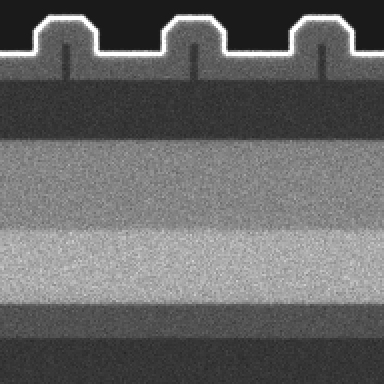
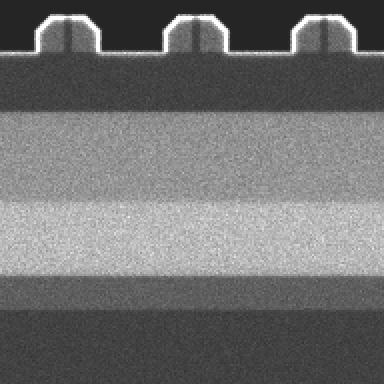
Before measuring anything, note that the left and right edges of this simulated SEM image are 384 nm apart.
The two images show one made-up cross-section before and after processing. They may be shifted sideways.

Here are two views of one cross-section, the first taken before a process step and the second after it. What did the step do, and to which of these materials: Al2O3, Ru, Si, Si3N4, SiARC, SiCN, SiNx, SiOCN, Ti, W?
It removed Si3N4.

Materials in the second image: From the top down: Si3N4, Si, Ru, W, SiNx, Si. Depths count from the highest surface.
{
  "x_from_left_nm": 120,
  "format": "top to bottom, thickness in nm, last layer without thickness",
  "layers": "empty 36, Si 60, Ru 90, W 74, SiNx 34, Si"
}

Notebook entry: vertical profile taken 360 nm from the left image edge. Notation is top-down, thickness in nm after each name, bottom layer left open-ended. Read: empty 36, Si 60, Ru 90, W 74, SiNx 34, Si